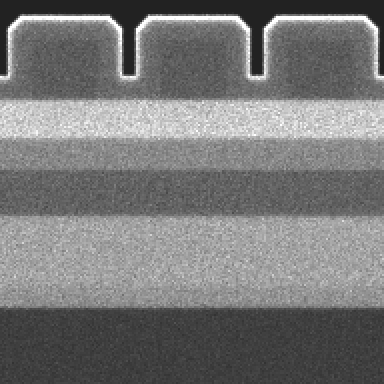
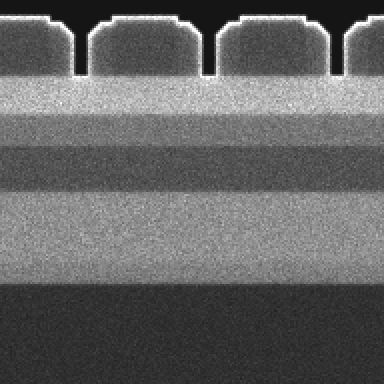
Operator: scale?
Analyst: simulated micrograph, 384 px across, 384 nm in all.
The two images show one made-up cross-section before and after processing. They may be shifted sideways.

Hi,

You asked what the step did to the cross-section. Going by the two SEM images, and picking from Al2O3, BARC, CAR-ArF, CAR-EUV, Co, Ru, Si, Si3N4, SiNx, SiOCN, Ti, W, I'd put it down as Si3N4, removed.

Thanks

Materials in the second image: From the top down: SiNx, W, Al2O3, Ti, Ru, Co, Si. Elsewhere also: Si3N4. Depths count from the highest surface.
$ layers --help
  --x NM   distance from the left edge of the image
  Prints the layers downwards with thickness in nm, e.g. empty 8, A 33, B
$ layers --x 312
empty 6, Si3N4 54, W 38, Al2O3 32, Ti 46, Ru 70, Co 22, Si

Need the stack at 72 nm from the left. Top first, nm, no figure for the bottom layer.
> empty 18, Si3N4 42, W 38, Al2O3 32, Ti 46, Ru 70, Co 22, Si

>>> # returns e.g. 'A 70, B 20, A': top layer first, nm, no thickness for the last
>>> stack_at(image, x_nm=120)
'SiNx 60, W 38, Al2O3 32, Ti 46, Ru 70, Co 22, Si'